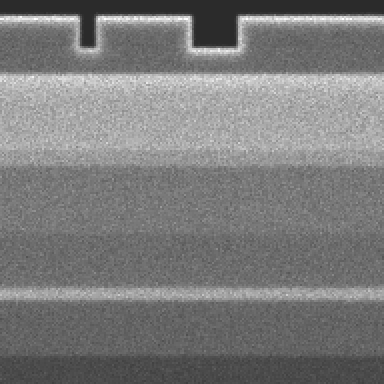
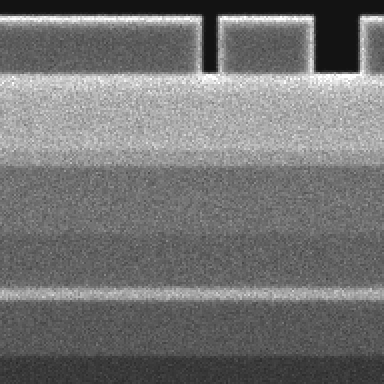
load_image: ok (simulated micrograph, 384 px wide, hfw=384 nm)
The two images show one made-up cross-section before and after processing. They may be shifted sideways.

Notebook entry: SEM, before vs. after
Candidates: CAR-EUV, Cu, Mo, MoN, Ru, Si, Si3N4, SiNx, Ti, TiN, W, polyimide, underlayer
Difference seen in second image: underlayer removed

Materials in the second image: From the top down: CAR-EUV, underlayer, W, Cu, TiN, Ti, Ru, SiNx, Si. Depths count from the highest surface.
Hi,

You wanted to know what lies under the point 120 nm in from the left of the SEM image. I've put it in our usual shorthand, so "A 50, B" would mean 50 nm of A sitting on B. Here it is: CAR-EUV 32, underlayer 26, W 76, Cu 16, TiN 68, Ti 54, Ru 12, SiNx 56, Si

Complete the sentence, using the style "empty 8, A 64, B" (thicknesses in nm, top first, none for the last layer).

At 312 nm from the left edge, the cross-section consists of CAR-EUV 32, underlayer 26, W 76, Cu 16, TiN 68, Ti 54, Ru 12, SiNx 56, Si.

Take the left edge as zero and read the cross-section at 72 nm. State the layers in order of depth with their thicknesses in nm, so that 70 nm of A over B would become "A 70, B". CAR-EUV 32, underlayer 26, W 76, Cu 16, TiN 68, Ti 54, Ru 12, SiNx 56, Si